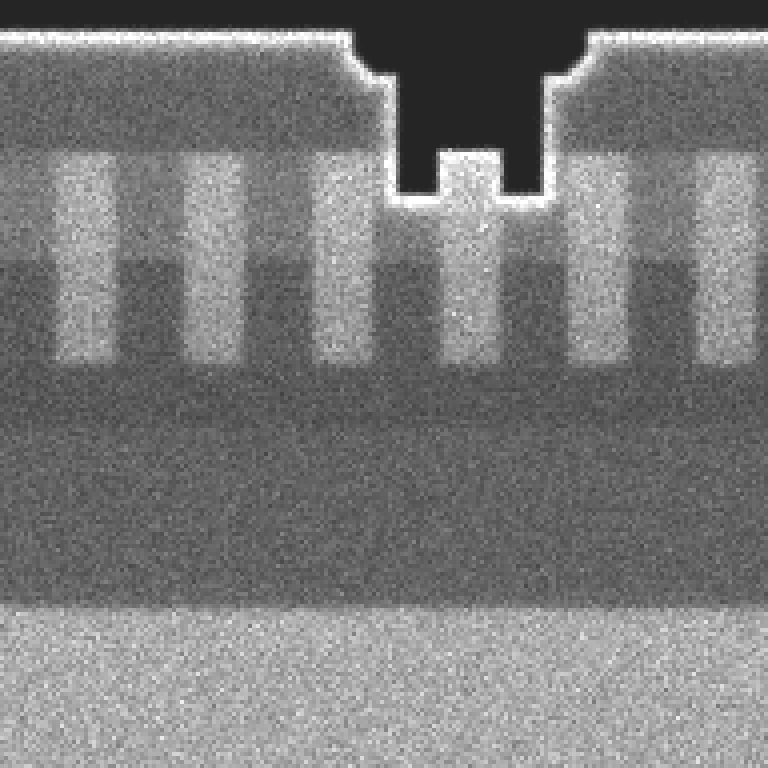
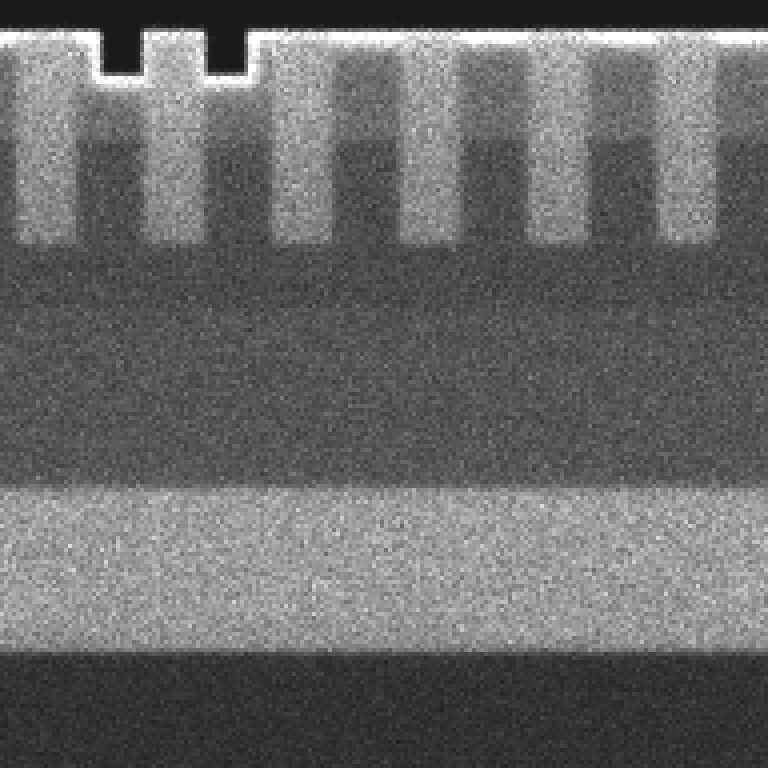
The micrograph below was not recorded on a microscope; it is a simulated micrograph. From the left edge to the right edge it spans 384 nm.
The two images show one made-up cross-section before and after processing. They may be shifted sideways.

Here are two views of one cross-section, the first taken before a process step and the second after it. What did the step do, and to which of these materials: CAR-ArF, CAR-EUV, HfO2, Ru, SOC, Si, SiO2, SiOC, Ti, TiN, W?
It removed SOC.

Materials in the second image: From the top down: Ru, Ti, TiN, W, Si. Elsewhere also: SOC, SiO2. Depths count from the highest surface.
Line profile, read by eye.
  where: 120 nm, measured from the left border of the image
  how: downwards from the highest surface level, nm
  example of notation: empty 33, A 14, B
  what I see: empty 22, SiO2 32, Ti 84, TiN 90, W 82, Si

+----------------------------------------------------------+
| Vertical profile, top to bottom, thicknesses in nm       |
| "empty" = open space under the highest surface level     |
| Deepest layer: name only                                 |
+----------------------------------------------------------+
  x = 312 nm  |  SiO2 54, Ti 84, TiN 90, W 82, Si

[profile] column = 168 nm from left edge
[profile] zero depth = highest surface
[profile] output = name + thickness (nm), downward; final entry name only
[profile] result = SiO2 54, Ti 84, TiN 90, W 82, Si